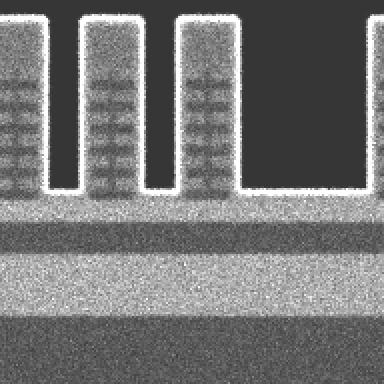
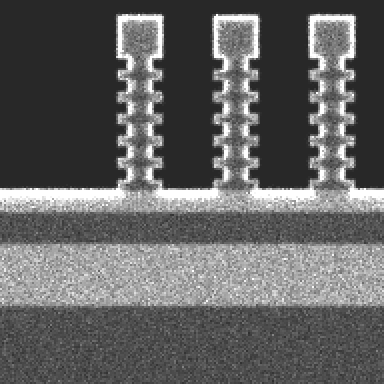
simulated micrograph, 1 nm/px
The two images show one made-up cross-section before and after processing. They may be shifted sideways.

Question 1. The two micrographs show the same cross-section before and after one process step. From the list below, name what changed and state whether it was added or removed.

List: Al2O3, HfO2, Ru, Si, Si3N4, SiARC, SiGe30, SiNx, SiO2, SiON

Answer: Si3N4, removed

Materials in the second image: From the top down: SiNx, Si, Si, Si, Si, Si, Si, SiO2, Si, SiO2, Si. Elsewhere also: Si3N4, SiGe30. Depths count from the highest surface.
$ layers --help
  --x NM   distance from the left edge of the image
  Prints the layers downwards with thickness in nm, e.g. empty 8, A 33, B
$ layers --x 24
empty 174, SiO2 22, Si 32, SiO2 62, Si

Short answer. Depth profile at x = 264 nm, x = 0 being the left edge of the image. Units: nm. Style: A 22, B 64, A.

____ empty 174, SiO2 22, Si 32, SiO2 62, Si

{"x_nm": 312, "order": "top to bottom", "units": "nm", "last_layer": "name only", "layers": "SiNx 42, empty 12, Si 10, empty 12, Si 10, empty 12, Si 10, empty 12, Si 10, empty 12, Si 10, empty 12, Si 10, SiO2 22, Si 32, SiO2 62, Si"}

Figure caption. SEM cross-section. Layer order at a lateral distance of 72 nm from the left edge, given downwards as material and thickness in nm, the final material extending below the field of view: empty 174, SiO2 22, Si 32, SiO2 62, Si